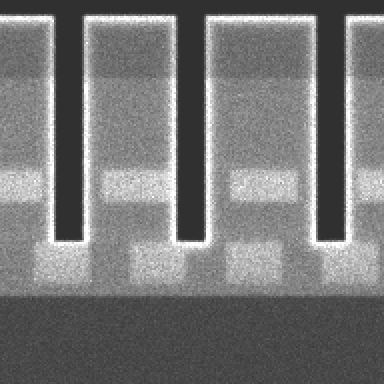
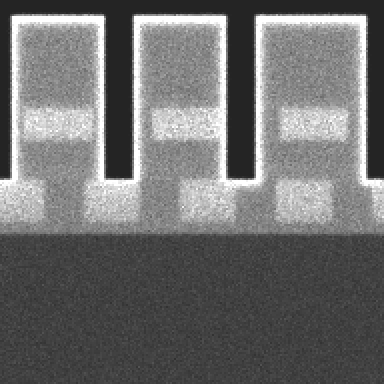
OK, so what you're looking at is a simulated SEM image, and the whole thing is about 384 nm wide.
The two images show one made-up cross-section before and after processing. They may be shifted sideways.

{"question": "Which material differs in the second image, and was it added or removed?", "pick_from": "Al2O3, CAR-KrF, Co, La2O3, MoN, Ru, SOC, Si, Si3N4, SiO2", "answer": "SOC, removed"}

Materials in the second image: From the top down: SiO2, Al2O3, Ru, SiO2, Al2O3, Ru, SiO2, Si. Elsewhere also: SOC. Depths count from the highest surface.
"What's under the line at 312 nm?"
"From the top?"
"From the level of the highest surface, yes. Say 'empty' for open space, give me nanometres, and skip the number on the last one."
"SiO2 84, Al2O3 8, Ru 32, SiO2 24, Al2O3 16, Ru 42, SiO2 12, Si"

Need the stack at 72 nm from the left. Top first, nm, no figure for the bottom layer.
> SiO2 84, Al2O3 8, Ru 32, SiO2 24, Al2O3 16, SiO2 54, Si